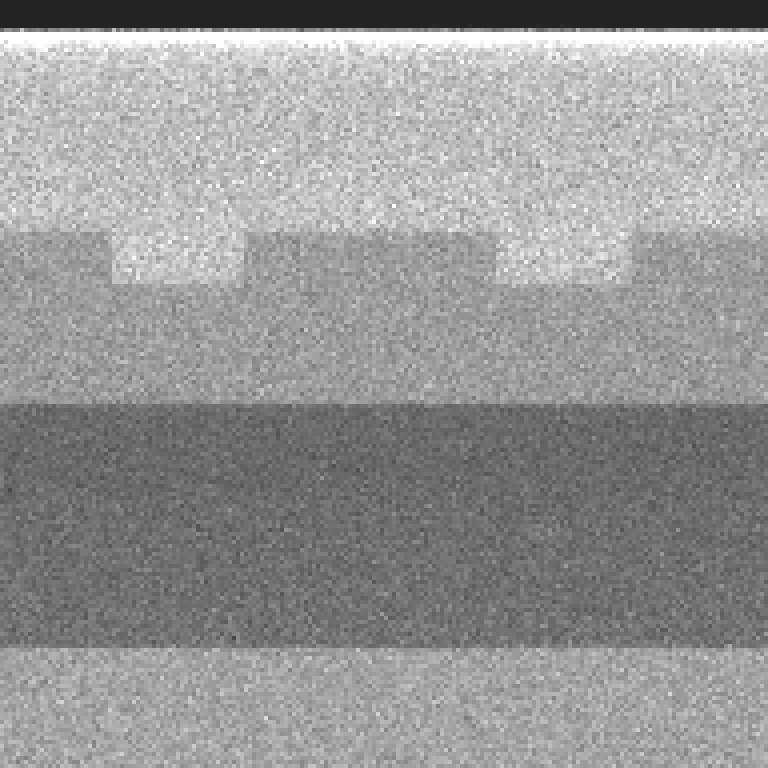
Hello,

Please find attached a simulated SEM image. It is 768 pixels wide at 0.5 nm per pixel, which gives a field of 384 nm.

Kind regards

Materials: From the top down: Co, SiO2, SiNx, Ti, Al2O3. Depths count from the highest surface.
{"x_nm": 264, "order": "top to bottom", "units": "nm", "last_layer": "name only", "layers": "Co 126, SiO2 60, SiNx 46, Ti 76, Al2O3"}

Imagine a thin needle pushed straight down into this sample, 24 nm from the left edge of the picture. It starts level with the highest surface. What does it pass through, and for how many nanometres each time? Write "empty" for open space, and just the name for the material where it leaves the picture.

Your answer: Co 100, SiO2 86, SiNx 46, Ti 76, Al2O3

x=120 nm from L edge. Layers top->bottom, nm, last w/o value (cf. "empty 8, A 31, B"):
Co 126, SiO2 60, SiNx 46, Ti 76, Al2O3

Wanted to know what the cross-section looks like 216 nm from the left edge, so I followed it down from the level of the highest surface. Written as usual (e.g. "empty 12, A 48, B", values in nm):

Co 100, SiO2 86, SiNx 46, Ti 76, Al2O3